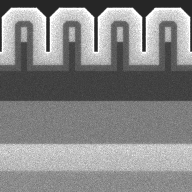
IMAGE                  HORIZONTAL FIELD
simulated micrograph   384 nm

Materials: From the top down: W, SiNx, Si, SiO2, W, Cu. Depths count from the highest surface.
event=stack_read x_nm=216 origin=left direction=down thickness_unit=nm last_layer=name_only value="W 114, SiNx 12, Si 60, SiO2 86, W 54, Cu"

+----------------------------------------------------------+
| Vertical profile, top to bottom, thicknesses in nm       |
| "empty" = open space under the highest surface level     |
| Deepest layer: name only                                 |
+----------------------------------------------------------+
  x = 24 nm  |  W 114, SiNx 12, Si 60, SiO2 86, W 54, Cu